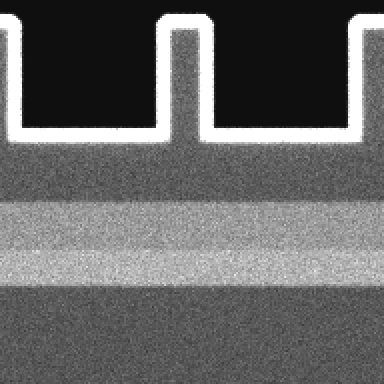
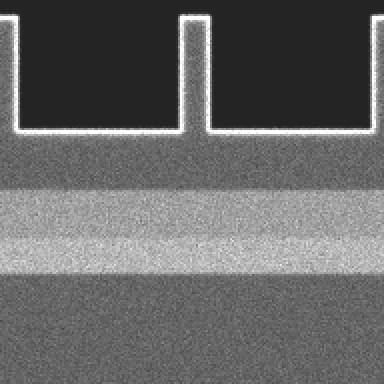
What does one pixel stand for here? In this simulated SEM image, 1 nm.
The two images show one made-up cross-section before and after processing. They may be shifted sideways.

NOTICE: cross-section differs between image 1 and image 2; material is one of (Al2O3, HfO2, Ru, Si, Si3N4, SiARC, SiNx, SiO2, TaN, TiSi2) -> removed: SiO2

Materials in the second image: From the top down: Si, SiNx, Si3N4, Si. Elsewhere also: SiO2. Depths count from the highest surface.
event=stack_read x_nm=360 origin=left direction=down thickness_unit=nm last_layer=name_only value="empty 114, Si 60, SiNx 48, Si3N4 36, Si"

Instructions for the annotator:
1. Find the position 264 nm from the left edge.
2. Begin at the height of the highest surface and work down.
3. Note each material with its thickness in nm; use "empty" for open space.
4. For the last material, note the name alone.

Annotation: empty 114, Si 60, SiNx 48, Si3N4 36, Si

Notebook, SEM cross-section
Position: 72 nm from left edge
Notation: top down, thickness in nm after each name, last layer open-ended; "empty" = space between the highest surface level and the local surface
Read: empty 114, Si 60, SiNx 48, Si3N4 36, Si